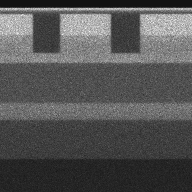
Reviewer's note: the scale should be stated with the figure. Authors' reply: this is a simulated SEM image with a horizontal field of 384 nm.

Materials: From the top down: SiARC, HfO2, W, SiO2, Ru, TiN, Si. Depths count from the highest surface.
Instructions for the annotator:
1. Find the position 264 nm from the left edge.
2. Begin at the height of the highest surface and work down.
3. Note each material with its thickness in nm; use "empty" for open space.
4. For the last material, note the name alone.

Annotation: SiARC 90, W 20, SiO2 80, Ru 34, TiN 78, Si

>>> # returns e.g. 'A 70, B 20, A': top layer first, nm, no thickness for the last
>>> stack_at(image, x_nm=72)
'SiARC 90, W 20, SiO2 80, Ru 34, TiN 78, Si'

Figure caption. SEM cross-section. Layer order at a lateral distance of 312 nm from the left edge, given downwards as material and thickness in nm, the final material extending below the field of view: SiARC 12, HfO2 42, W 56, SiO2 80, Ru 34, TiN 78, Si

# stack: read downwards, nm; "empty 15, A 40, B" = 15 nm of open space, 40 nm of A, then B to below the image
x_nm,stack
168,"SiARC 12, HfO2 42, W 56, SiO2 80, Ru 34, TiN 78, Si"